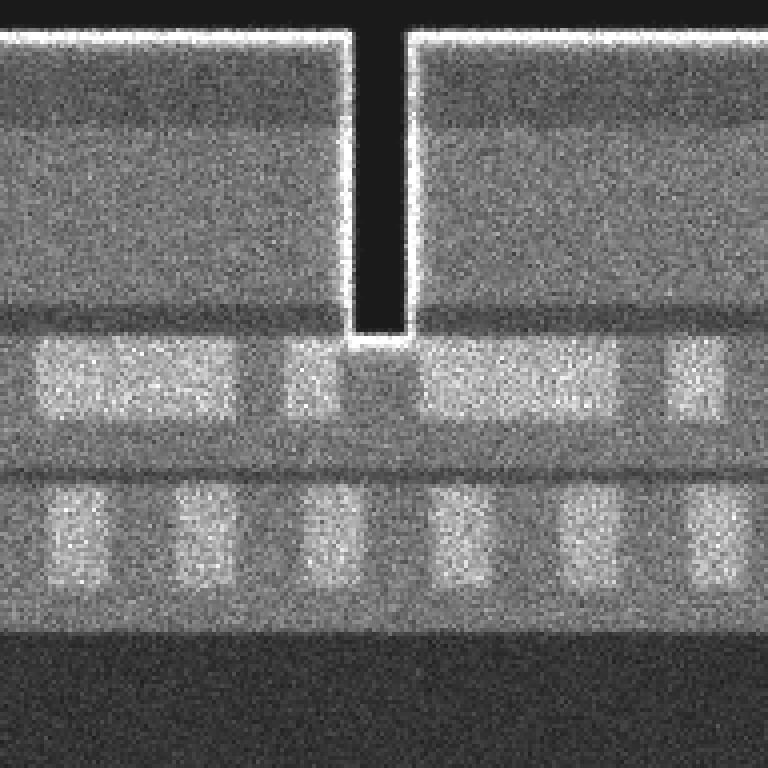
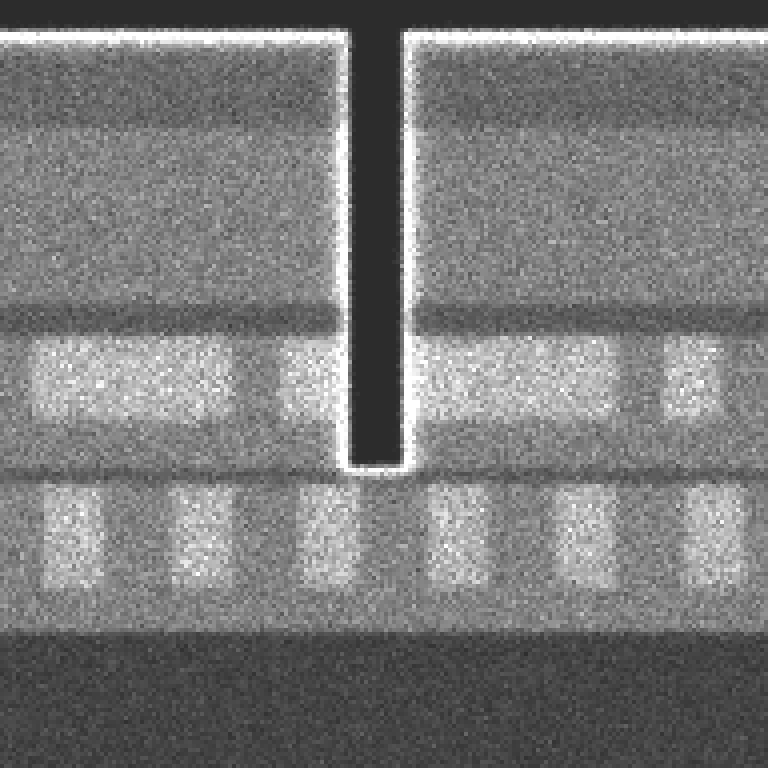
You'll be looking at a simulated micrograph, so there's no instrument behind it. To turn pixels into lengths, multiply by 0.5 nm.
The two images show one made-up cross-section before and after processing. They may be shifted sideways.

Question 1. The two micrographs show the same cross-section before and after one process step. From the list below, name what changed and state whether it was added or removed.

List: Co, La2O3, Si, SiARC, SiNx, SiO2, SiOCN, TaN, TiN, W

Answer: SiO2, removed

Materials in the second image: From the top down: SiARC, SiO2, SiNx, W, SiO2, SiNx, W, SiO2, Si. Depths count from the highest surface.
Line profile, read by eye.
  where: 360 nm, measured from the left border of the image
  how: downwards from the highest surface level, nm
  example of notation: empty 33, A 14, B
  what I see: SiARC 48, SiO2 88, SiNx 16, SiO2 66, SiNx 8, W 52, SiO2 22, Si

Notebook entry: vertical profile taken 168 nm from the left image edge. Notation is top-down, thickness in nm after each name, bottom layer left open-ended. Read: SiARC 48, SiO2 88, SiNx 16, SiO2 66, SiNx 8, W 52, SiO2 22, Si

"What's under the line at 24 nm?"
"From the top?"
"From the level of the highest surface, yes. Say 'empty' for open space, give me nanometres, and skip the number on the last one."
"SiARC 48, SiO2 88, SiNx 16, W 42, SiO2 24, SiNx 8, W 52, SiO2 22, Si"